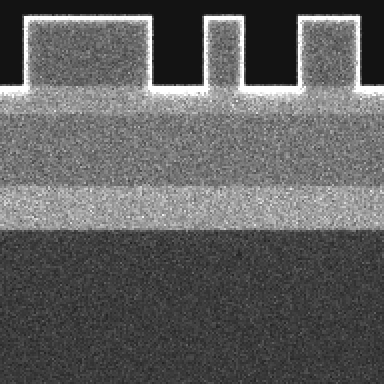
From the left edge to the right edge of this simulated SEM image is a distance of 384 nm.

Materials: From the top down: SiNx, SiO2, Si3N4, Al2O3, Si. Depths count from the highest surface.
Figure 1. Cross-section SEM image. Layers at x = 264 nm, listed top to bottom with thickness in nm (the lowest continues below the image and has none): empty 70, SiO2 28, Si3N4 72, Al2O3 44, Si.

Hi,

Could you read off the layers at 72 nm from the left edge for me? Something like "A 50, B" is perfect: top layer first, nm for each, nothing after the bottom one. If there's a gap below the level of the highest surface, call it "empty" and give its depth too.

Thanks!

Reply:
SiNx 70, SiO2 28, Si3N4 72, Al2O3 44, Si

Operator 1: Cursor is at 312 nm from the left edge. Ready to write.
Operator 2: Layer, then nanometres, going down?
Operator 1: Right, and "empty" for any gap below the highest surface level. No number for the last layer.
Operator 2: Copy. SiNx 70, SiO2 28, Si3N4 72, Al2O3 44, Si